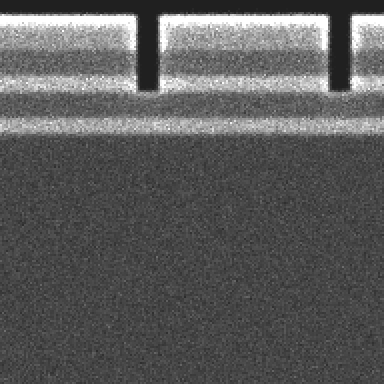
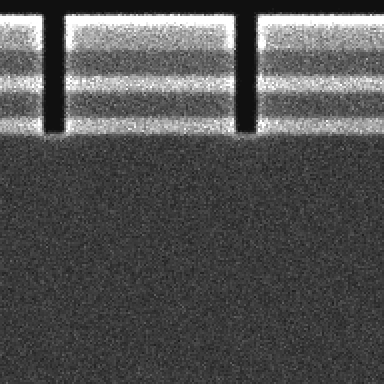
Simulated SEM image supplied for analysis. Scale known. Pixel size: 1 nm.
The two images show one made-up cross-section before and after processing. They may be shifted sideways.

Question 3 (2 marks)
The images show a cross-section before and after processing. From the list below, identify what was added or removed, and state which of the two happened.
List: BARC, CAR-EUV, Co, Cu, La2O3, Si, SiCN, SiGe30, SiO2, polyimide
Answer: Co and SiGe30 was removed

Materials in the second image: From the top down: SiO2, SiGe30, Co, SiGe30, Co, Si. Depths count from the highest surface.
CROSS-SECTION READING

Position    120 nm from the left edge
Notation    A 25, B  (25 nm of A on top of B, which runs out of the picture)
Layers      SiO2 34, SiGe30 26, Co 16, SiGe30 26, Co 16, Si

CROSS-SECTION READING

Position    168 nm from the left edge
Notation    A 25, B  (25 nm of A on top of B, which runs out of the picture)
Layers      SiO2 34, SiGe30 26, Co 16, SiGe30 26, Co 16, Si